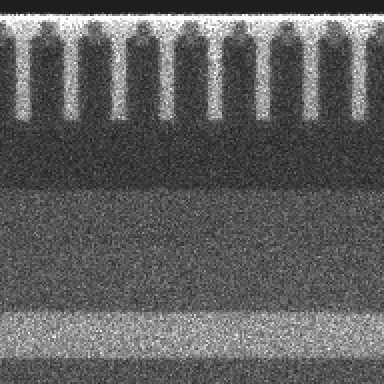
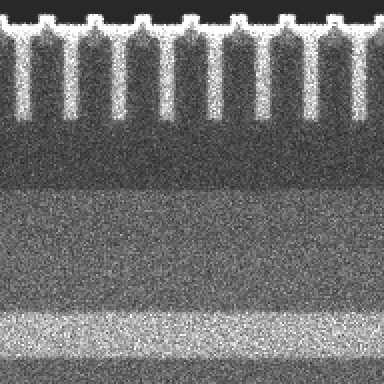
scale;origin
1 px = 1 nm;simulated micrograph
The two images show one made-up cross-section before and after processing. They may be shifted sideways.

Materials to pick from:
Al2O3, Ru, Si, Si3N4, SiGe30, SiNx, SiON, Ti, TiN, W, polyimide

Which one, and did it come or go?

W - removed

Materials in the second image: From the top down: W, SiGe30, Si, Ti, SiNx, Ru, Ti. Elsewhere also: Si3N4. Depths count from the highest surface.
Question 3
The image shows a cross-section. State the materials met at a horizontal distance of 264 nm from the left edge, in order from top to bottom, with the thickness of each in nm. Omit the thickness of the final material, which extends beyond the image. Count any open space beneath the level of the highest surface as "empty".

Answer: empty 10, W 94, SiGe30 10, Si 60, Ti 58, SiNx 64, Ru 46, Ti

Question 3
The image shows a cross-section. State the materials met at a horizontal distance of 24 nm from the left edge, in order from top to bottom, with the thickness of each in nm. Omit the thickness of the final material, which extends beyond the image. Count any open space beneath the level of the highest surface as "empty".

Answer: empty 10, W 94, SiGe30 10, Si 60, Ti 58, SiNx 64, Ru 46, Ti